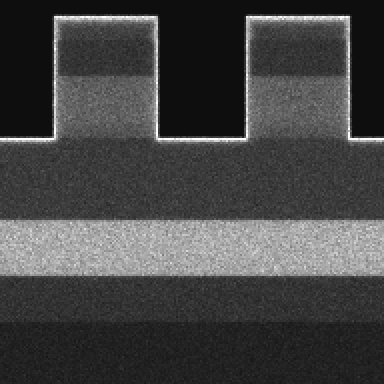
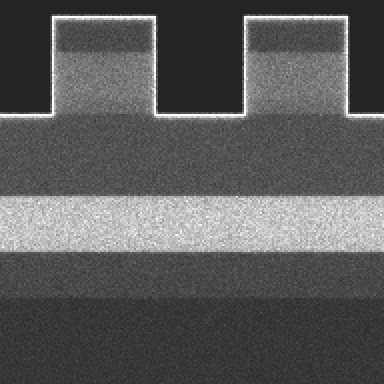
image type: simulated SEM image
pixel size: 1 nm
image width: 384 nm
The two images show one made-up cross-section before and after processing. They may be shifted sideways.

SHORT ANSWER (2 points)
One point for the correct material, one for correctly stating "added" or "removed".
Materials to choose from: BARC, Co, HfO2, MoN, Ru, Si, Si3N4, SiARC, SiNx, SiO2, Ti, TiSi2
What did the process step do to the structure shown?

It removed SiARC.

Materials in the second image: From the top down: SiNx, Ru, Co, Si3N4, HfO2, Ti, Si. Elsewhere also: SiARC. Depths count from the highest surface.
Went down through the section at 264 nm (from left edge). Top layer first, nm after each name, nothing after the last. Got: SiNx 36, Ru 48, Co 14, Si3N4 82, HfO2 56, Ti 46, Si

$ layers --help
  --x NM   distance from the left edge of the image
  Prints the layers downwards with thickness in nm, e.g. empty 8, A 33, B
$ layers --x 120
SiNx 36, Ru 48, Co 14, Si3N4 82, HfO2 56, Ti 46, Si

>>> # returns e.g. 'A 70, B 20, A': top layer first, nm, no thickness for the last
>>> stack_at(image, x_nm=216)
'empty 98, Si3N4 82, HfO2 56, Ti 46, Si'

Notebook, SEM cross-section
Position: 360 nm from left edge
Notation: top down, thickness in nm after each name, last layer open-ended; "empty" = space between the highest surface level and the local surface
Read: empty 98, Si3N4 82, HfO2 56, Ti 46, Si